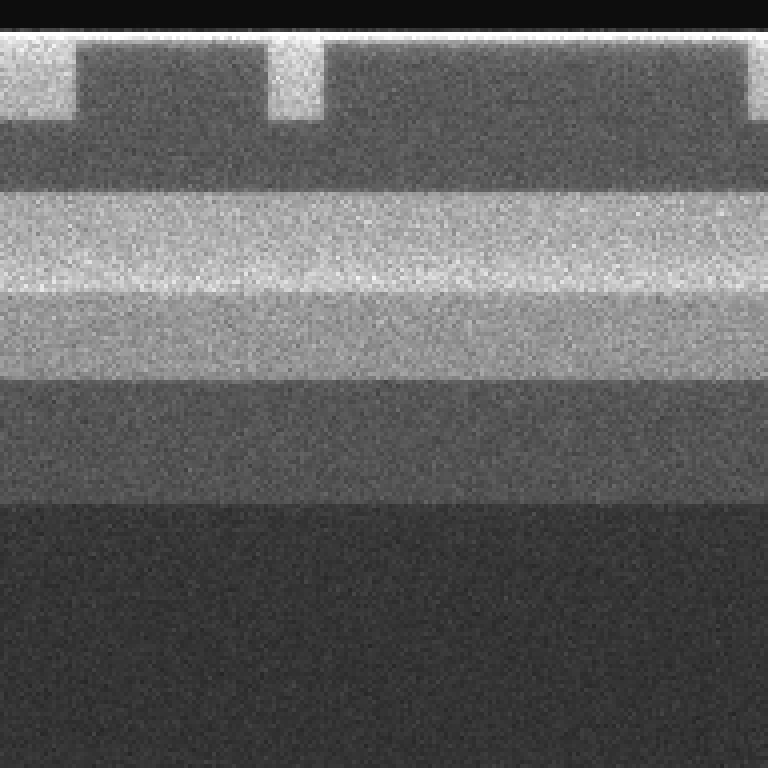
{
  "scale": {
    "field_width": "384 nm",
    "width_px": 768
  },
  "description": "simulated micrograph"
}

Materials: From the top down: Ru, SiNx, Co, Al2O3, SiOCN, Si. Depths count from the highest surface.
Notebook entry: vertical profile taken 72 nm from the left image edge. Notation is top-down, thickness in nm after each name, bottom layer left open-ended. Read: SiNx 80, Co 50, Al2O3 44, SiOCN 62, Si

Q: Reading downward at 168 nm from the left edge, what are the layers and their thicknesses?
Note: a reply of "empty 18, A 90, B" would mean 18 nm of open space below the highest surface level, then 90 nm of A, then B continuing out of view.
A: SiNx 80, Co 50, Al2O3 44, SiOCN 62, Si